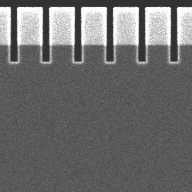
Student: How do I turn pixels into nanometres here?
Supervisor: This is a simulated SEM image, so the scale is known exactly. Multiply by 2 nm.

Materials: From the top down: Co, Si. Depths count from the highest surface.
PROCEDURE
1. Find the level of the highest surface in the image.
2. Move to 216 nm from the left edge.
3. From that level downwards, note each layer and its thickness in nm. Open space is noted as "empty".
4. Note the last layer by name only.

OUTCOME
empty 108, Si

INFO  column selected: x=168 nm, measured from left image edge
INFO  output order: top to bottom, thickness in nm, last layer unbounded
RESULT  Co 74, Si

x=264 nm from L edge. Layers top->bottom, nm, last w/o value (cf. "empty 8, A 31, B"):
Co 74, Si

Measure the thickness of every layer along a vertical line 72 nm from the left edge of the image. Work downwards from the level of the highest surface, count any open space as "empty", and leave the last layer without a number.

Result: Co 74, Si